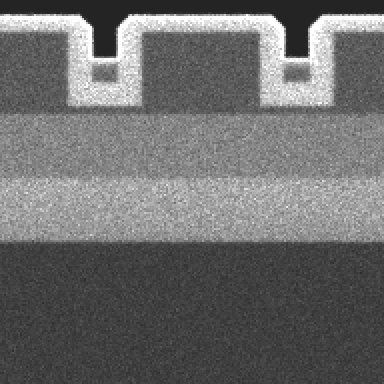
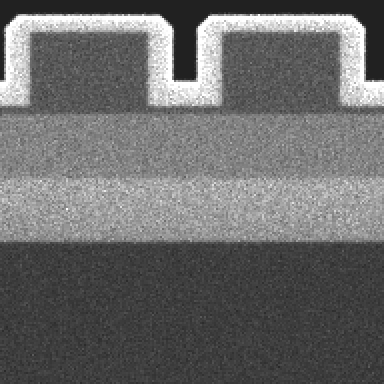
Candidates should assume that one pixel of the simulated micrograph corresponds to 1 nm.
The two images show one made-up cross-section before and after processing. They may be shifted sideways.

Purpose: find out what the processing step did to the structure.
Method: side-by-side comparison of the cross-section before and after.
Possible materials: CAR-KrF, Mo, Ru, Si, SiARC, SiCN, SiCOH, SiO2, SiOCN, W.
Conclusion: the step removed SiARC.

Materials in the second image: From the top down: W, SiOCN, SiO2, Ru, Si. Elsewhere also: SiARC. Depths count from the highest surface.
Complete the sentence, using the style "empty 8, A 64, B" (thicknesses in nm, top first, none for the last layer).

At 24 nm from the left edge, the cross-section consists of W 90, SiOCN 8, SiO2 64, Ru 64, Si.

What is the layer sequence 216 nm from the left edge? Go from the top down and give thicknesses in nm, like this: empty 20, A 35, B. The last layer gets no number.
W 90, SiOCN 8, SiO2 64, Ru 64, Si